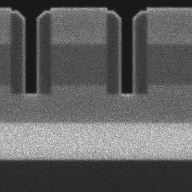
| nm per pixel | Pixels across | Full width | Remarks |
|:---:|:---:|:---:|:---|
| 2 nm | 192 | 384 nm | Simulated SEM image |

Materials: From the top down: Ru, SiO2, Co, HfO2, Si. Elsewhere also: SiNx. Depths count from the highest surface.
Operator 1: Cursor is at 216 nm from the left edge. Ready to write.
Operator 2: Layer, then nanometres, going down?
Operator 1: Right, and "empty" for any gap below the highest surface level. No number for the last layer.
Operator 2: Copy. empty 6, SiNx 166, Co 58, HfO2 74, Si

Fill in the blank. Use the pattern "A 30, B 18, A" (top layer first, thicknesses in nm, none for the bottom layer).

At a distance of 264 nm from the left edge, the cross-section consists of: empty 172, Co 58, HfO2 74, Si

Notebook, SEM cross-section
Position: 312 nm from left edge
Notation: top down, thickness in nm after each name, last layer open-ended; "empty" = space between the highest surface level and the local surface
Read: Ru 72, SiO2 82, Co 76, HfO2 74, Si